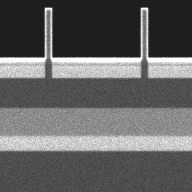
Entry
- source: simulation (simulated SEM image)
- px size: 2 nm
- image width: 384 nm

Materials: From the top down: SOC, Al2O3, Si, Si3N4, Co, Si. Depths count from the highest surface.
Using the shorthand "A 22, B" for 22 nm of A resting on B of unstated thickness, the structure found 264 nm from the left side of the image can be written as empty 100, SOC 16, Al2O3 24, Si 60, Si3N4 56, Co 30, Si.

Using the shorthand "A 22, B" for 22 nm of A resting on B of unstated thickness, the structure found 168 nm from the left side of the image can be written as empty 100, SOC 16, Al2O3 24, Si 60, Si3N4 56, Co 30, Si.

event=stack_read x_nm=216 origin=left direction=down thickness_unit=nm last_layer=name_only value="empty 100, SOC 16, Al2O3 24, Si 60, Si3N4 56, Co 30, Si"